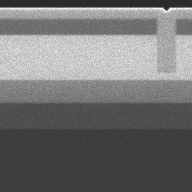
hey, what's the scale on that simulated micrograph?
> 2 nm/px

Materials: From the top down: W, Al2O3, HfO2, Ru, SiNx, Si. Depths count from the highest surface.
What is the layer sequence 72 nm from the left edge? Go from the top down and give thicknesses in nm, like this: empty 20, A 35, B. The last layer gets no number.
W 22, Al2O3 32, HfO2 90, Ru 46, SiNx 52, Si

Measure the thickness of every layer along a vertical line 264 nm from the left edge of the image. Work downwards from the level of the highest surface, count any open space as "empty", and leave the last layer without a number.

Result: W 22, Al2O3 32, HfO2 90, Ru 46, SiNx 52, Si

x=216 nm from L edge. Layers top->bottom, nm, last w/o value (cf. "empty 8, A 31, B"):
W 22, Al2O3 32, HfO2 90, Ru 46, SiNx 52, Si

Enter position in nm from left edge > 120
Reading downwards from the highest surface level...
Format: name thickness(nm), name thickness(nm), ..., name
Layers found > W 22, Al2O3 32, HfO2 90, Ru 46, SiNx 52, Si